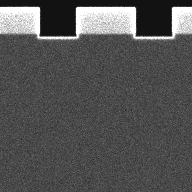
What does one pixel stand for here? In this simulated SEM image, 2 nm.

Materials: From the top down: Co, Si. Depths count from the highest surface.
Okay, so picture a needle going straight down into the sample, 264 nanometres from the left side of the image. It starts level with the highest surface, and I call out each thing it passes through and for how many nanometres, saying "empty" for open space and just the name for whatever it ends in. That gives Co 52, Si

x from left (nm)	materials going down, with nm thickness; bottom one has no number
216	Co 52, Si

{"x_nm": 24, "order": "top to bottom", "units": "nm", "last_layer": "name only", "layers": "Co 52, Si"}